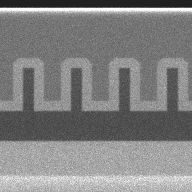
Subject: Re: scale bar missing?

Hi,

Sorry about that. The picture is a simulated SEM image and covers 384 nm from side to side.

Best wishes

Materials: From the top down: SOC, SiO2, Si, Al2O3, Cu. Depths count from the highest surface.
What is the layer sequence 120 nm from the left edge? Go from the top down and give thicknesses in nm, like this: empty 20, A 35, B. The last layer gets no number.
SOC 186, SiO2 20, Si 60, Al2O3 70, Cu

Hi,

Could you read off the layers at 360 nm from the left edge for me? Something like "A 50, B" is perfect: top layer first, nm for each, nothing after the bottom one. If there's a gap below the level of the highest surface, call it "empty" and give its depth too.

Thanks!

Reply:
SOC 100, SiO2 106, Si 60, Al2O3 70, Cu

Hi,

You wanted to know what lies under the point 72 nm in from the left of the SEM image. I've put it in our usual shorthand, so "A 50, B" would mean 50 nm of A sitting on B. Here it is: SOC 100, SiO2 106, Si 60, Al2O3 70, Cu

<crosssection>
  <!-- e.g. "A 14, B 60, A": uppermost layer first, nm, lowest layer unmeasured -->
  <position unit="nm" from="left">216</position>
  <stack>SOC 186, SiO2 20, Si 60, Al2O3 70, Cu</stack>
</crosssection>